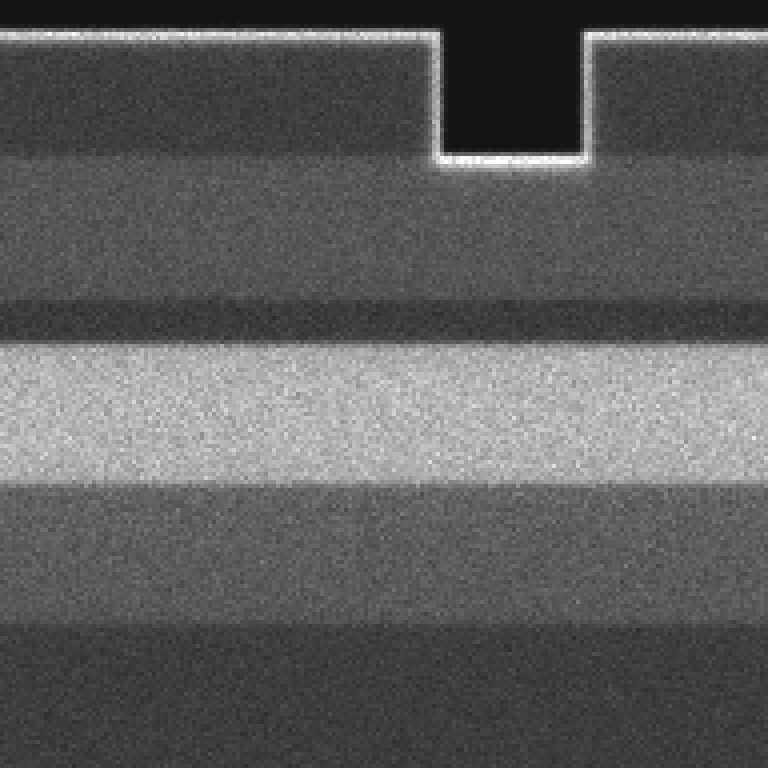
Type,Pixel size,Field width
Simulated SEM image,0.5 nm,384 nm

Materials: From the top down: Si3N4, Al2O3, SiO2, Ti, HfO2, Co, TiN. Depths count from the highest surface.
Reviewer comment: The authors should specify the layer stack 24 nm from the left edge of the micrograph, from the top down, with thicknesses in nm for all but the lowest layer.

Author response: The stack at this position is Si3N4 62, Al2O3 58, SiO2 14, Ti 22, HfO2 70, Co 70, TiN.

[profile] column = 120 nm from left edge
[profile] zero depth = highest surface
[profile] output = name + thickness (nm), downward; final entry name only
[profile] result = Si3N4 62, Al2O3 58, SiO2 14, Ti 22, HfO2 70, Co 70, TiN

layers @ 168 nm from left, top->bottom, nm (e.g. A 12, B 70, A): Si3N4 62, Al2O3 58, SiO2 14, Ti 22, HfO2 70, Co 70, TiN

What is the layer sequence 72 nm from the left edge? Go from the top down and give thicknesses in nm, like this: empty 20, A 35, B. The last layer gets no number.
Si3N4 62, Al2O3 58, SiO2 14, Ti 22, HfO2 70, Co 70, TiN